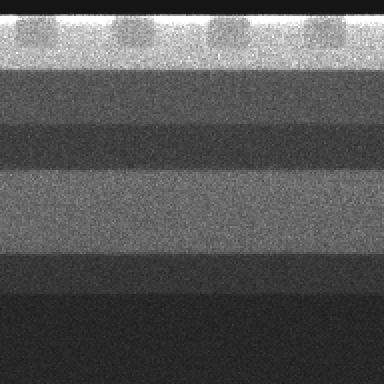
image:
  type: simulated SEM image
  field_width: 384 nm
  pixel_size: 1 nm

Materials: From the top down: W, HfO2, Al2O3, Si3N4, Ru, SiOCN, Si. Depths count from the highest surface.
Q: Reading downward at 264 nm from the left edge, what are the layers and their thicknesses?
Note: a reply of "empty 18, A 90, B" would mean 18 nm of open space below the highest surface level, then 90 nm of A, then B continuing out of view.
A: HfO2 54, Al2O3 54, Si3N4 46, Ru 84, SiOCN 40, Si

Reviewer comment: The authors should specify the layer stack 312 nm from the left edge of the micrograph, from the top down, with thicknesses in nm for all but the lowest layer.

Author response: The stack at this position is W 32, HfO2 22, Al2O3 54, Si3N4 46, Ru 84, SiOCN 40, Si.